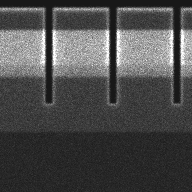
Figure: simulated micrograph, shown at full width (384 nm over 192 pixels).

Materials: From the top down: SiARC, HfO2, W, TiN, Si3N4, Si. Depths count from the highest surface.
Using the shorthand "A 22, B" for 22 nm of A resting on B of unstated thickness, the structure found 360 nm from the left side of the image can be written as empty 192, TiN 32, Si3N4 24, Si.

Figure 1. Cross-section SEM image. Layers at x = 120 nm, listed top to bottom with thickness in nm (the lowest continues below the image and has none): SiARC 44, HfO2 70, W 24, TiN 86, Si3N4 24, Si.